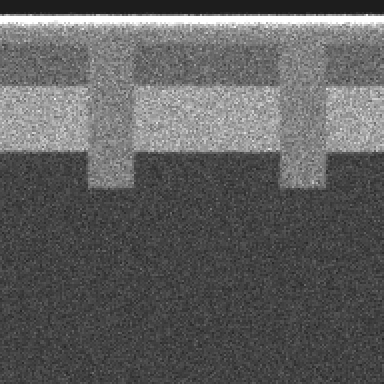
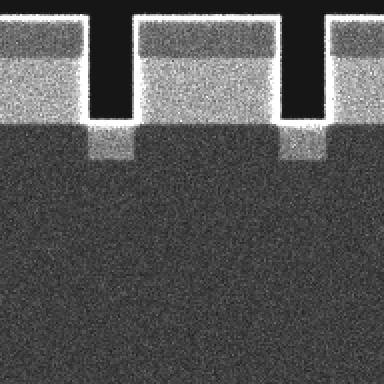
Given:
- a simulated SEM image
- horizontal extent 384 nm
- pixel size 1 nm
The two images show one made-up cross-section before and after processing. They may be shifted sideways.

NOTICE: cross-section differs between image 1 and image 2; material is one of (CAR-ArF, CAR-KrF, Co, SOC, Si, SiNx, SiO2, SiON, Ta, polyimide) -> removed: SOC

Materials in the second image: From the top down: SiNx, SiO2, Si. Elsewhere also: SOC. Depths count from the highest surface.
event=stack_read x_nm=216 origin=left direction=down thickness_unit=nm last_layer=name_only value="SiNx 42, SiO2 66, Si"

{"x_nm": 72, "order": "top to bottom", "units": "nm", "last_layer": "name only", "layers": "SiNx 42, SiO2 66, Si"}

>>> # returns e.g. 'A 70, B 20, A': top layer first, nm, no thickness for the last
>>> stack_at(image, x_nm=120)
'empty 104, SOC 40, Si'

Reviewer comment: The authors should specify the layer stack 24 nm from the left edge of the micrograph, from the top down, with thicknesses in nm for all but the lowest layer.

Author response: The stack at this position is SiNx 42, SiO2 66, Si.